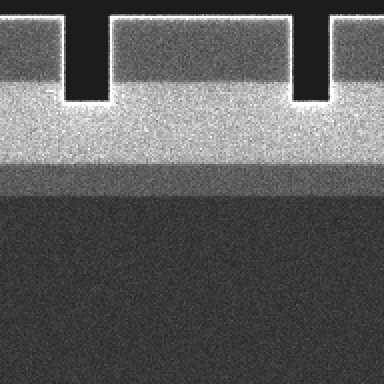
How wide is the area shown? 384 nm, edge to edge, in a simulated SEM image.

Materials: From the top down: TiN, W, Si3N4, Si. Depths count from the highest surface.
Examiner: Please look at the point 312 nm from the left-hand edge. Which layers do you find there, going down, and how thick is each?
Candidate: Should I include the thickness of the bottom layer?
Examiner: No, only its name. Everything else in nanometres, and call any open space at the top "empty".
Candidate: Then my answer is empty 86, W 62, Si3N4 32, Si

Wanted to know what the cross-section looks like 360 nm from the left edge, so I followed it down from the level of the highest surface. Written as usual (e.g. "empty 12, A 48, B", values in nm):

TiN 66, W 82, Si3N4 32, Si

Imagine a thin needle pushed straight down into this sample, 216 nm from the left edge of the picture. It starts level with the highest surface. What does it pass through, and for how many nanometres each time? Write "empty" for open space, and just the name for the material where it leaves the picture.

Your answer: TiN 66, W 82, Si3N4 32, Si